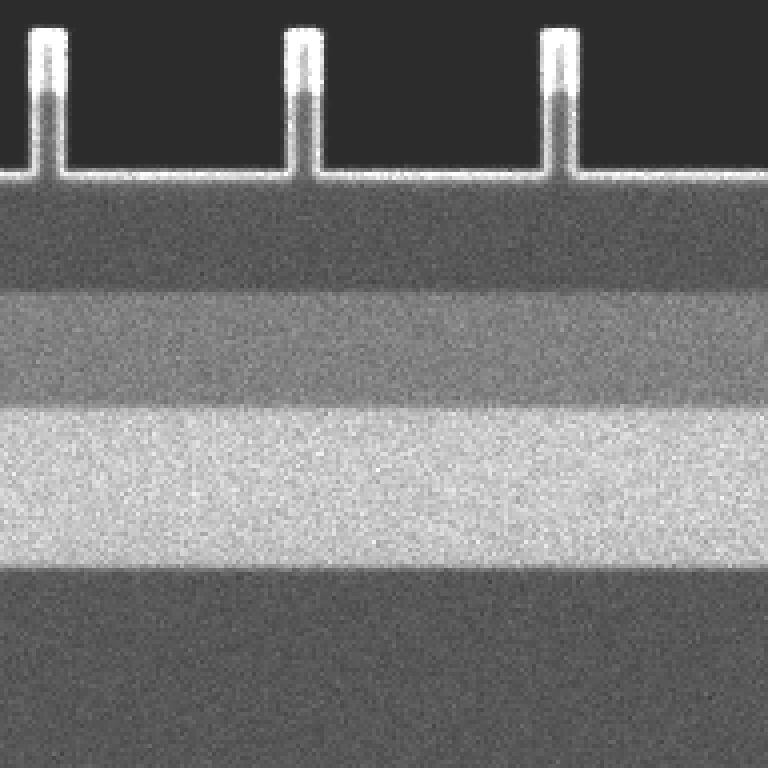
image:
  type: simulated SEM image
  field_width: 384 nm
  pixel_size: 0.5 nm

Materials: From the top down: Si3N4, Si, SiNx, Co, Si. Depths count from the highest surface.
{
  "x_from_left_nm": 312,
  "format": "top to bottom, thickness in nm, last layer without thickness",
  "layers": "empty 70, Si 60, SiNx 58, Co 80, Si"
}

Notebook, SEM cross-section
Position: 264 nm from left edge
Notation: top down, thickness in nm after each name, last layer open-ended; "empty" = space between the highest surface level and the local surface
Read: empty 70, Si 60, SiNx 58, Co 80, Si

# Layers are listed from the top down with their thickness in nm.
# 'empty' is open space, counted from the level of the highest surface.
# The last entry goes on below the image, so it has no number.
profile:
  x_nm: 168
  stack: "empty 70, Si 60, SiNx 58, Co 80, Si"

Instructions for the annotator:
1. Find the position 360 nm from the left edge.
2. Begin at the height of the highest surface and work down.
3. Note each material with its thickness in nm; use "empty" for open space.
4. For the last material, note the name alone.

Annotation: empty 70, Si 60, SiNx 58, Co 80, Si